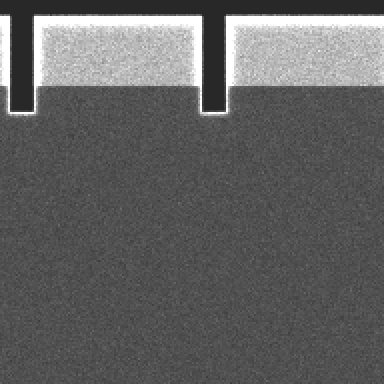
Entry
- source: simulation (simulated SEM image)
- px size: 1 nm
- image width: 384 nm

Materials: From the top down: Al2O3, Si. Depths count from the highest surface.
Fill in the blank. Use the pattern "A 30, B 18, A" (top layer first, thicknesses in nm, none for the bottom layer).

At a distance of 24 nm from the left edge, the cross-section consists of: empty 96, Si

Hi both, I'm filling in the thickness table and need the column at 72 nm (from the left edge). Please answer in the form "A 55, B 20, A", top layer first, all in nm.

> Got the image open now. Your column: Al2O3 70, Si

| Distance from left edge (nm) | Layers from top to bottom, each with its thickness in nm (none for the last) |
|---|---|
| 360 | Al2O3 70, Si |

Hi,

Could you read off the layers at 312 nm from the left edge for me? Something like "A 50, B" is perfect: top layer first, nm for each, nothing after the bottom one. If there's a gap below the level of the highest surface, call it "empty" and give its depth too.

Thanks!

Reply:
Al2O3 70, Si